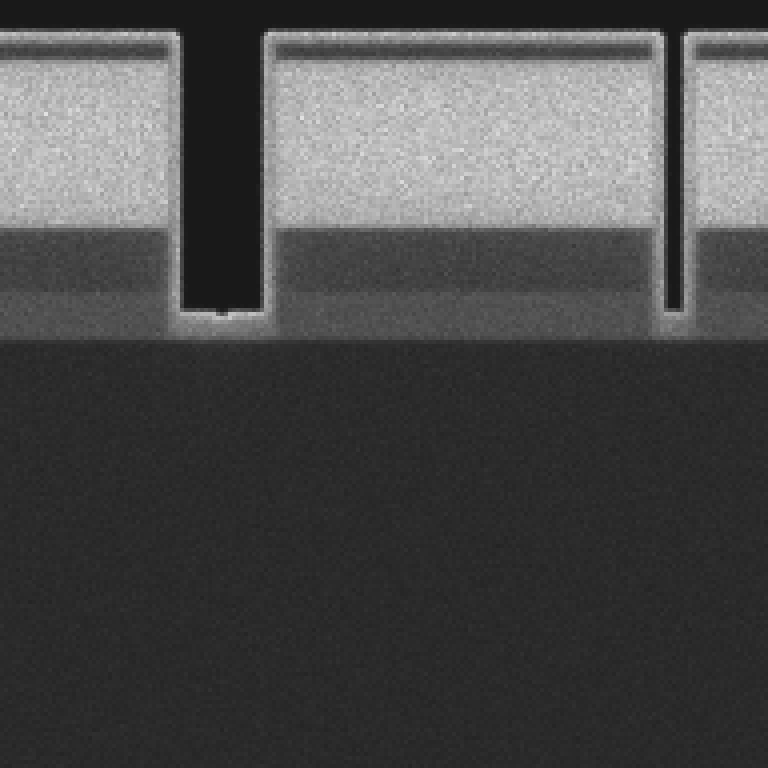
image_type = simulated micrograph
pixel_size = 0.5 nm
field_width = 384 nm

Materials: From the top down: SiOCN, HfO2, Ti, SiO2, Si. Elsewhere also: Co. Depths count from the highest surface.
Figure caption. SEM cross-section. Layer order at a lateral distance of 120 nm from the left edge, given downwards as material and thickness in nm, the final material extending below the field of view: empty 140, Co 12, Si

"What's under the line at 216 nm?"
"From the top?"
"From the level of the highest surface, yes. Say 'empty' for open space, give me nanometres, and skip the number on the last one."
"SiOCN 14, HfO2 84, Ti 32, SiO2 24, Si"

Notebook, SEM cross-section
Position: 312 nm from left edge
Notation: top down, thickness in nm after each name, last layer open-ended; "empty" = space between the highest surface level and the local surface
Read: SiOCN 14, HfO2 84, Ti 32, SiO2 24, Si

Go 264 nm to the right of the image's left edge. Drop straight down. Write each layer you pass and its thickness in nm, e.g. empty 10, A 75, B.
SiOCN 14, HfO2 84, Ti 32, SiO2 24, Si